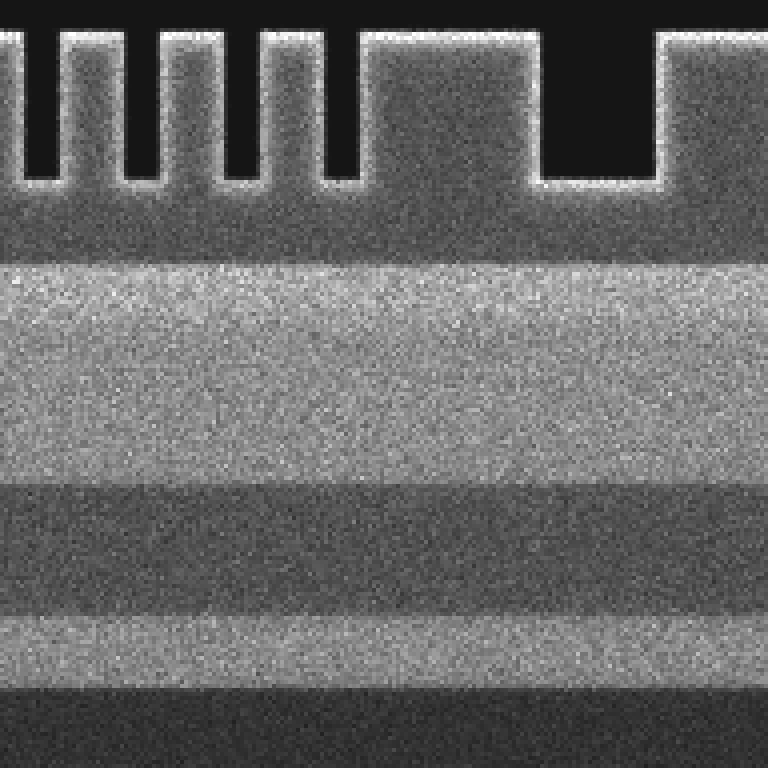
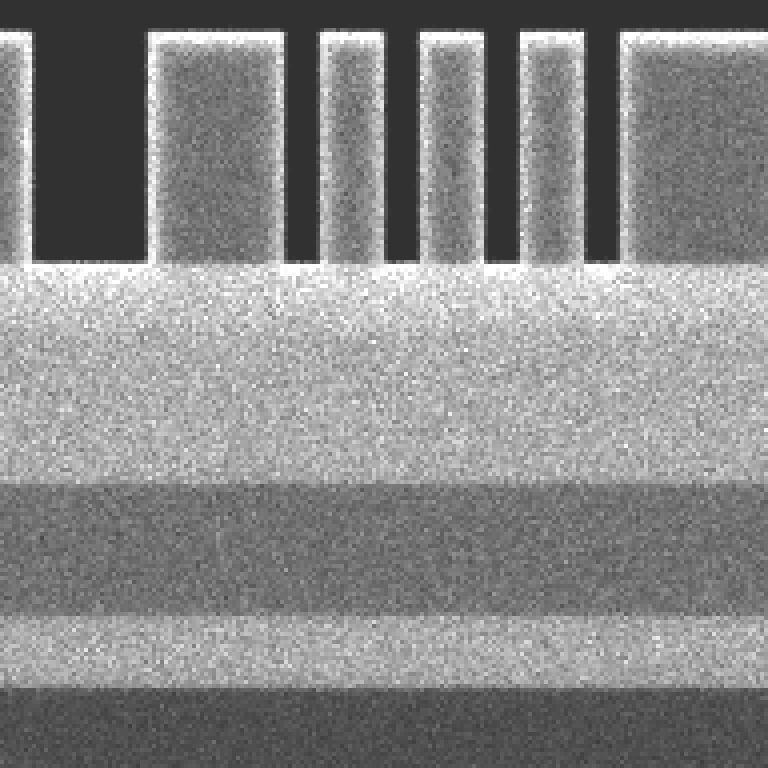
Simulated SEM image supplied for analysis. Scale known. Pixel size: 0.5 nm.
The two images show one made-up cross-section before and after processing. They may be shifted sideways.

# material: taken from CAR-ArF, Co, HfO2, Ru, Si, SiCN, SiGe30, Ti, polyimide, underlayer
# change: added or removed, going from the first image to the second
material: underlayer
change: removed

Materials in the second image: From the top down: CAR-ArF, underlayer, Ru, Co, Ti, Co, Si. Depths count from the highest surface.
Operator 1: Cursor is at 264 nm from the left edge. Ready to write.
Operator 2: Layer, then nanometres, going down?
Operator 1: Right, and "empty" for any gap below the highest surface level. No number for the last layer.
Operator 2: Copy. CAR-ArF 74, underlayer 42, Ru 30, Co 80, Ti 66, Co 36, Si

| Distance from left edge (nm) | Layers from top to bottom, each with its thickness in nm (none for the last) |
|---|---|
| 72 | empty 116, Ru 30, Co 80, Ti 66, Co 36, Si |